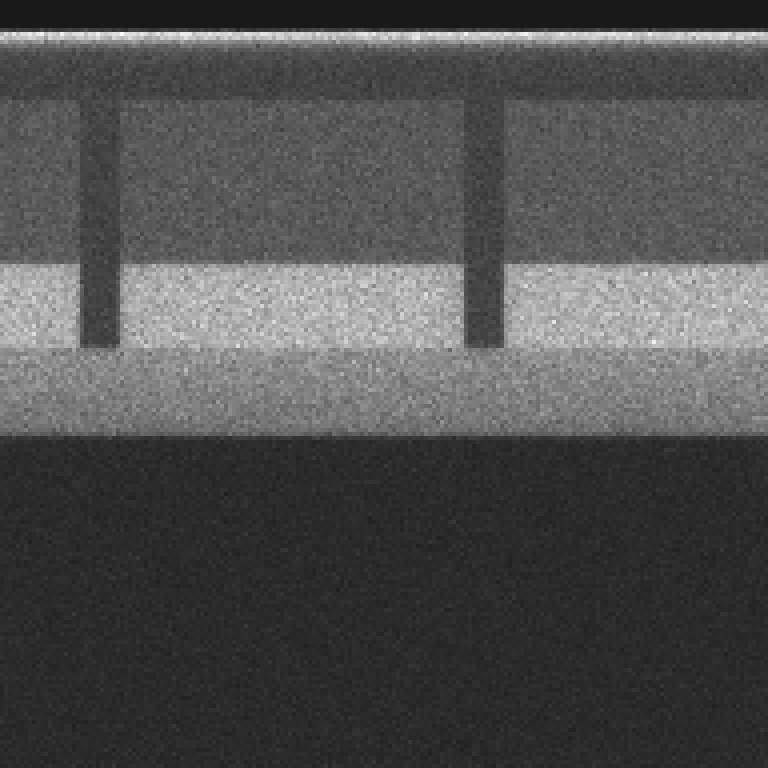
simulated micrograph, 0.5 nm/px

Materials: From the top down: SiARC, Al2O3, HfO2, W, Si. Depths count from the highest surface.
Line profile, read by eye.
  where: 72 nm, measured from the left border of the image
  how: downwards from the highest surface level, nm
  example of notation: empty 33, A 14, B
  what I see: SiARC 34, Al2O3 82, HfO2 42, W 44, Si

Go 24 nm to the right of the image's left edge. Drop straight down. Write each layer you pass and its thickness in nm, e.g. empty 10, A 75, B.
SiARC 34, Al2O3 82, HfO2 42, W 44, Si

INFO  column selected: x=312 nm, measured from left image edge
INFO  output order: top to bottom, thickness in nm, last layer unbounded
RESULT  SiARC 34, Al2O3 82, HfO2 42, W 44, Si